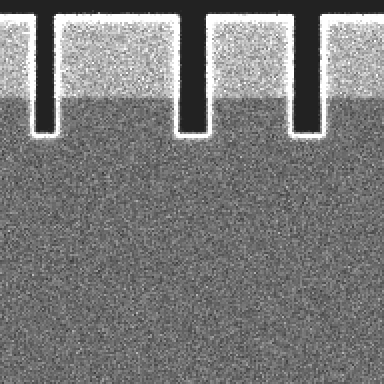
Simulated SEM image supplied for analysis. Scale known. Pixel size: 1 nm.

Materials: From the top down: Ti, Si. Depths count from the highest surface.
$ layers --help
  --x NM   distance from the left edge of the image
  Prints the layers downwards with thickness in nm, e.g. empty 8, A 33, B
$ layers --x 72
Ti 82, Si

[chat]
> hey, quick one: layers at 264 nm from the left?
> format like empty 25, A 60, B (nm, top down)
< Ti 82, Si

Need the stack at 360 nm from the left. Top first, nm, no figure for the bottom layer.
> Ti 82, Si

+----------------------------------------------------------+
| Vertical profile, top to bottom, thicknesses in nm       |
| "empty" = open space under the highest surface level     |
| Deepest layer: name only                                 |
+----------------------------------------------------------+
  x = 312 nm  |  empty 118, Si